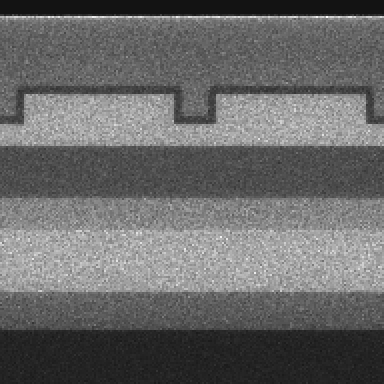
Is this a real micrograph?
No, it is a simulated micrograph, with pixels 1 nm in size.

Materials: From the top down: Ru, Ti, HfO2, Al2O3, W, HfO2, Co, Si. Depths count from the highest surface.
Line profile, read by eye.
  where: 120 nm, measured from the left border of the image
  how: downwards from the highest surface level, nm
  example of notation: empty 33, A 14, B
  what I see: Ru 70, Ti 8, HfO2 52, Al2O3 52, W 32, HfO2 62, Co 38, Si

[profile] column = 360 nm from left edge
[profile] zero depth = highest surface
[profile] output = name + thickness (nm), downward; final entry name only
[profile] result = Ru 70, Ti 8, HfO2 52, Al2O3 52, W 32, HfO2 62, Co 38, Si